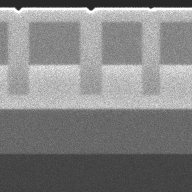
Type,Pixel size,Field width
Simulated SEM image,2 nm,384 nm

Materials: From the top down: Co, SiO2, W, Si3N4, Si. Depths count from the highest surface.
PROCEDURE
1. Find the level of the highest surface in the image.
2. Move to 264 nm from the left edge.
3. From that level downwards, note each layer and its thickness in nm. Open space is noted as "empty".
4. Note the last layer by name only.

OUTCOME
Co 28, SiO2 86, W 88, Si3N4 90, Si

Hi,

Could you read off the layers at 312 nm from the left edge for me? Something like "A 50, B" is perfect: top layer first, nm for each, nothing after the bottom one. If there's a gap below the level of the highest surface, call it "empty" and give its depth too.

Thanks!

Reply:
Co 174, W 28, Si3N4 90, Si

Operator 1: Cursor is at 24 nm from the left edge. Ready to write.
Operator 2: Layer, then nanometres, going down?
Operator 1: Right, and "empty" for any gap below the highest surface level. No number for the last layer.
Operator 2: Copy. Co 174, W 28, Si3N4 90, Si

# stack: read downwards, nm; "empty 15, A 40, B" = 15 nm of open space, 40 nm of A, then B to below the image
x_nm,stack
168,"Co 174, W 28, Si3N4 90, Si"